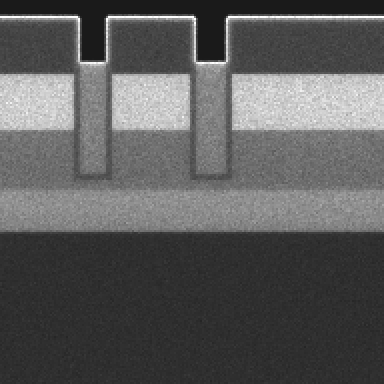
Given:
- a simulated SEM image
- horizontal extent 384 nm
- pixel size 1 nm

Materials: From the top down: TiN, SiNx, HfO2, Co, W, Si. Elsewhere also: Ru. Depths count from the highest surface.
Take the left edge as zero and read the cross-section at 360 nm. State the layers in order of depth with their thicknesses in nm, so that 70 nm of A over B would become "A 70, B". TiN 6, SiNx 52, HfO2 56, Co 60, W 42, Si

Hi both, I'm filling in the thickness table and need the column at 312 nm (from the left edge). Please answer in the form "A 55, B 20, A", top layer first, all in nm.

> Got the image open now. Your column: TiN 6, SiNx 52, HfO2 56, Co 60, W 42, Si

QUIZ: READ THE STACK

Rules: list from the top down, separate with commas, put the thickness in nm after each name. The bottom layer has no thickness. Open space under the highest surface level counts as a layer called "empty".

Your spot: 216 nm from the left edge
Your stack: empty 46, Ru 112, TiN 6, Co 10, W 42, Si